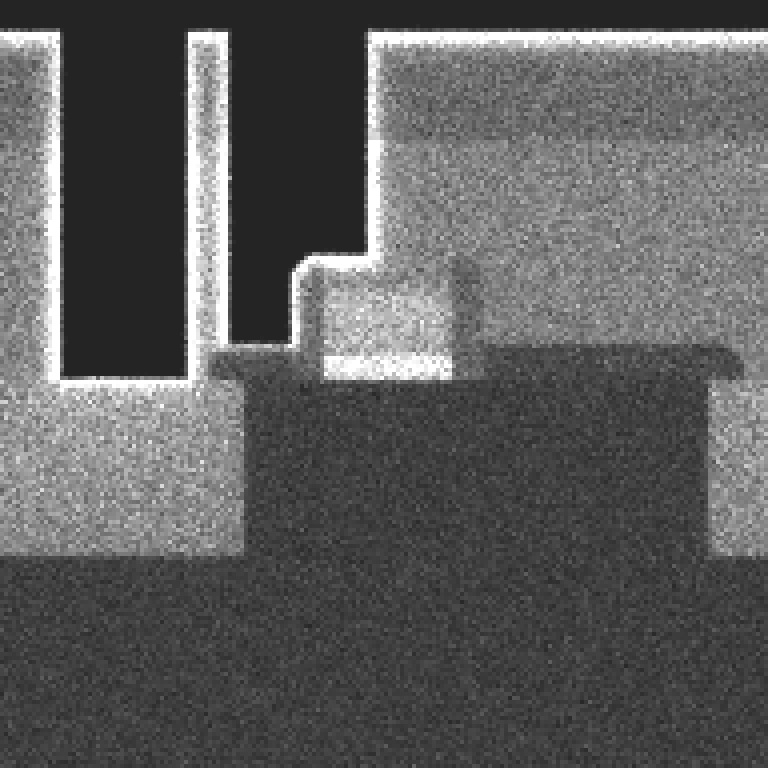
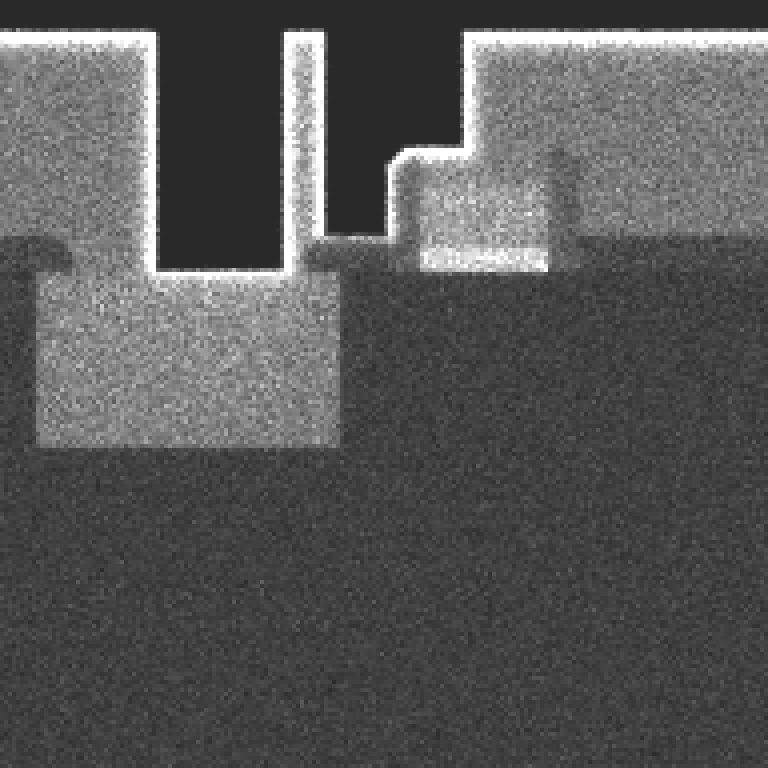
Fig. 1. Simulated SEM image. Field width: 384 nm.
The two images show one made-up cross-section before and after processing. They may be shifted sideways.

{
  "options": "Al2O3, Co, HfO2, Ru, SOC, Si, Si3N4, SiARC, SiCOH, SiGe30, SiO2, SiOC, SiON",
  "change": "removed",
  "material": "SOC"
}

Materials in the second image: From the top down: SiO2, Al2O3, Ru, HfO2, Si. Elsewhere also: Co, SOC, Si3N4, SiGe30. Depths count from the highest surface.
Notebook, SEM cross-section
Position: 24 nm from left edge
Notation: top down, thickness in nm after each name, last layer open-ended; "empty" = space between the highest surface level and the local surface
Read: SiO2 102, SiGe30 18, Co 88, Si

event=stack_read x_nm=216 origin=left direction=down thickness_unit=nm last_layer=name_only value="empty 58, Al2O3 18, Ru 32, HfO2 12, Si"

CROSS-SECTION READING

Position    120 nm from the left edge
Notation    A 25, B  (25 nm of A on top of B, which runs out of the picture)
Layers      empty 120, Co 88, Si